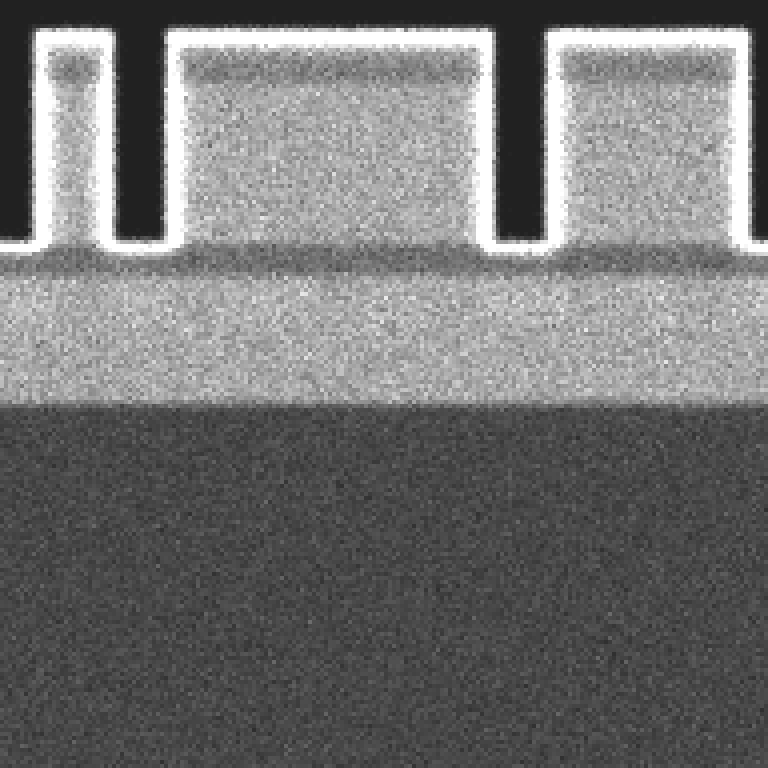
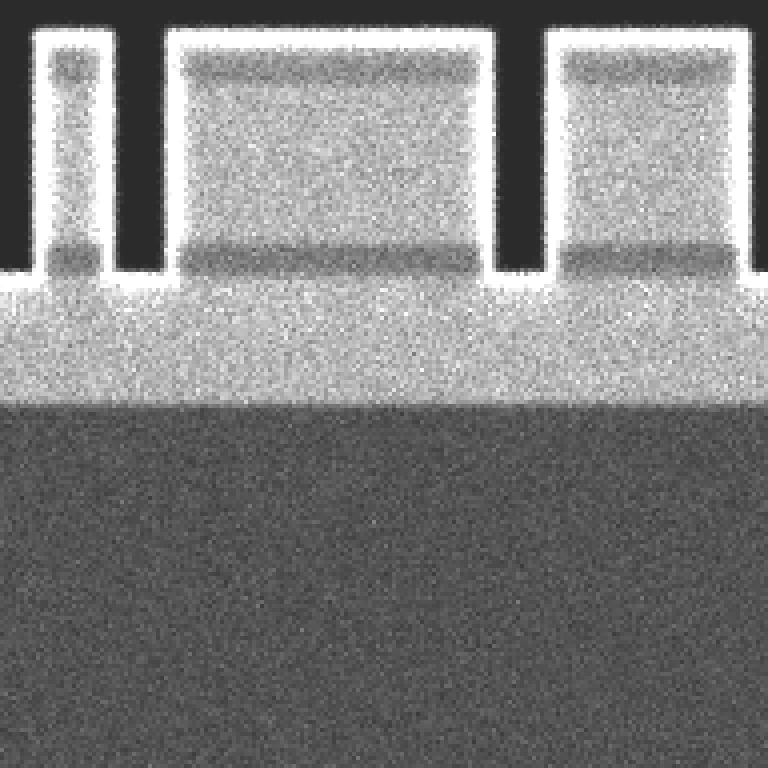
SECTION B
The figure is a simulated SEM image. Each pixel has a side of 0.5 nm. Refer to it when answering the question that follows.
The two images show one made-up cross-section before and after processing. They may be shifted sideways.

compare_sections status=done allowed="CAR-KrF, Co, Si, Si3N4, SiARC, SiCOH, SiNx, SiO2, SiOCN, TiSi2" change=removed material="SiNx"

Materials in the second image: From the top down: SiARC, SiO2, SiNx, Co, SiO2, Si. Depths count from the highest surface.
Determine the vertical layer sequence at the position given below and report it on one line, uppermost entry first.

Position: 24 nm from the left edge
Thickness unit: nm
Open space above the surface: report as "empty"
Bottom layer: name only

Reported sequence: SiARC 26, SiO2 80, SiNx 16, Co 24, SiO2 40, Si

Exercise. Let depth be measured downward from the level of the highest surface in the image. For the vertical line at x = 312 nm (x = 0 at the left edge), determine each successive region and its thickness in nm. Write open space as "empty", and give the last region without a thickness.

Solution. SiARC 26, SiO2 80, SiNx 16, Co 24, SiO2 40, Si